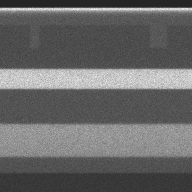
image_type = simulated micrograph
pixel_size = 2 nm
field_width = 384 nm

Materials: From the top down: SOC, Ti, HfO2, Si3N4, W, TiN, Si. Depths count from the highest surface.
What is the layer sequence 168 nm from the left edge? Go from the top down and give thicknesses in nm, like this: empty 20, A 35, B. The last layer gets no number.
SOC 34, Ti 88, HfO2 40, Si3N4 70, W 66, TiN 32, Si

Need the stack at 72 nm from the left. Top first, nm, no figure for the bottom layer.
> SOC 80, Ti 42, HfO2 40, Si3N4 70, W 66, TiN 32, Si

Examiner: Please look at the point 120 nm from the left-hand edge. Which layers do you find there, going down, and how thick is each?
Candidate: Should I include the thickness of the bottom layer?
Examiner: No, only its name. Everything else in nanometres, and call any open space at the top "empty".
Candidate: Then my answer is SOC 34, Ti 88, HfO2 40, Si3N4 70, W 66, TiN 32, Si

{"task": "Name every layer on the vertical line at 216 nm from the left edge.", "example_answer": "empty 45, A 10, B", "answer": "SOC 34, Ti 88, HfO2 40, Si3N4 70, W 66, TiN 32, Si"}